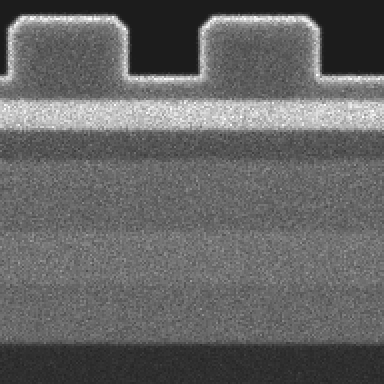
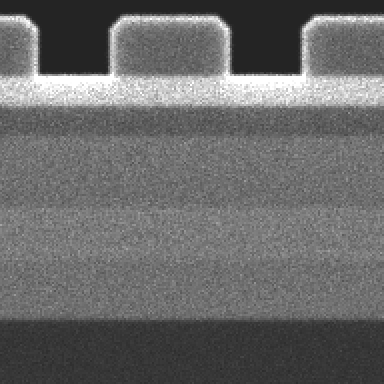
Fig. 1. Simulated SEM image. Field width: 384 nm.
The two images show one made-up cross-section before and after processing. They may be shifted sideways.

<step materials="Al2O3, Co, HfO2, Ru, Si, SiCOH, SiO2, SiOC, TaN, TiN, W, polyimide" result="removed Al2O3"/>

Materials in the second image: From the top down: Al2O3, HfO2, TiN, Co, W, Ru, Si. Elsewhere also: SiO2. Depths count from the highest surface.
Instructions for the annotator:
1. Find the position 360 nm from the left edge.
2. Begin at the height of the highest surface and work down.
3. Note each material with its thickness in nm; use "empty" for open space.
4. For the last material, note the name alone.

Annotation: SiO2 60, HfO2 30, TiN 30, Co 72, W 52, Ru 60, Si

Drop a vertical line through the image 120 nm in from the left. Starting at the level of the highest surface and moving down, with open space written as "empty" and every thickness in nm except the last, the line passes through empty 2, Al2O3 58, HfO2 30, TiN 30, Co 72, W 52, Ru 60, Si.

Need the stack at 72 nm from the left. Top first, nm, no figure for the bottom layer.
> empty 60, HfO2 30, TiN 30, Co 72, W 52, Ru 60, Si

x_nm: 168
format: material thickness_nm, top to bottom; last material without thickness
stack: SiO2 60, HfO2 30, TiN 30, Co 72, W 52, Ru 60, Si